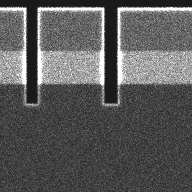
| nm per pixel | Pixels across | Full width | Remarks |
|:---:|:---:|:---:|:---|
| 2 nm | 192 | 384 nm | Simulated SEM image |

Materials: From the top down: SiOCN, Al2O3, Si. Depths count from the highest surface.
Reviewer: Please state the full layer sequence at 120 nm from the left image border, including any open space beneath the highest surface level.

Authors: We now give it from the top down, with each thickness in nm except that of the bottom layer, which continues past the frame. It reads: SiOCN 86, Al2O3 66, Si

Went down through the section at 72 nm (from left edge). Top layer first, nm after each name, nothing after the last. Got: empty 192, Si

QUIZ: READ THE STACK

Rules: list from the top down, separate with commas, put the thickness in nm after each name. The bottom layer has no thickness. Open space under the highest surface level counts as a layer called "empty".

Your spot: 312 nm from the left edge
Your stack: SiOCN 86, Al2O3 66, Si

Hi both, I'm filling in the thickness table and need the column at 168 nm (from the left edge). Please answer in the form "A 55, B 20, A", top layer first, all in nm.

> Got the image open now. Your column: SiOCN 86, Al2O3 66, Si